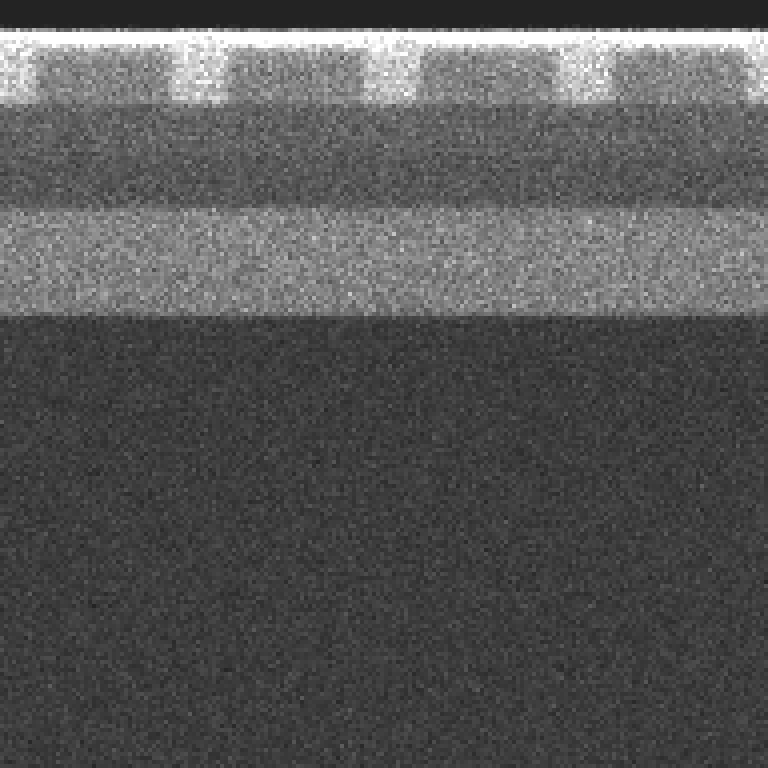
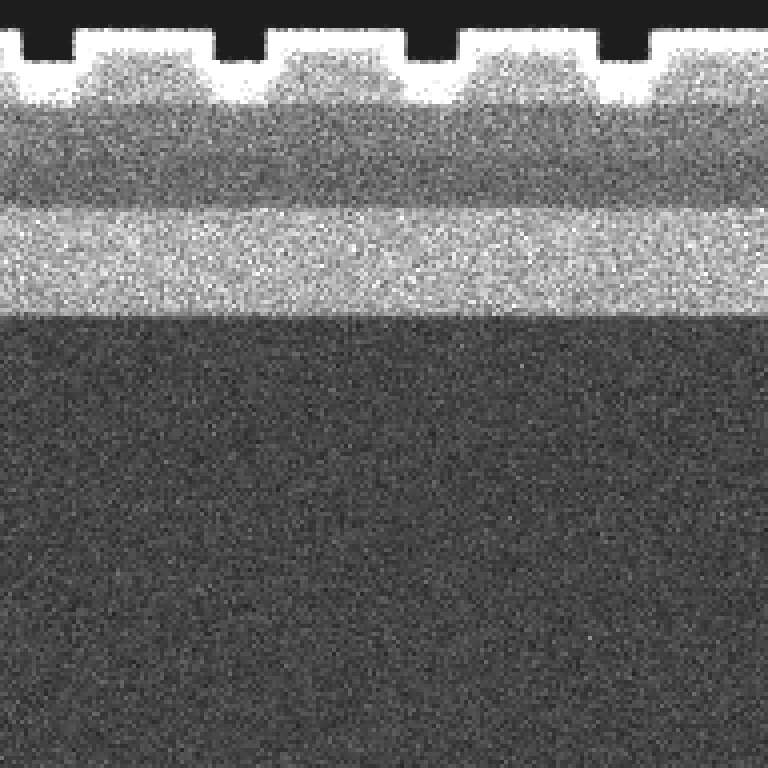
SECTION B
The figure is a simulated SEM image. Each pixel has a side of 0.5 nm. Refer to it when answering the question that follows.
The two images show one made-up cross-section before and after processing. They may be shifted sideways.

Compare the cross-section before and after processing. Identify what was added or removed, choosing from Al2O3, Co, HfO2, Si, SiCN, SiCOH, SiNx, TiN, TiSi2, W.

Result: W removed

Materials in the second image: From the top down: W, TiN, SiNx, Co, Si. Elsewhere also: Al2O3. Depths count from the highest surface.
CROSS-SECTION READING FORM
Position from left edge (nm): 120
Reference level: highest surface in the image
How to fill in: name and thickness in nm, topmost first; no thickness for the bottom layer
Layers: empty 16, W 20, TiN 26, SiNx 26, Co 54, Si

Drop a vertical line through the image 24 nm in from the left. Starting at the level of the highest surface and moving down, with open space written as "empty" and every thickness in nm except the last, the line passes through empty 16, W 20, TiN 26, SiNx 26, Co 54, Si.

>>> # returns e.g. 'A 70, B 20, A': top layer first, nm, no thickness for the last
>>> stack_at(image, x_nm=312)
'empty 16, W 20, TiN 26, SiNx 26, Co 54, Si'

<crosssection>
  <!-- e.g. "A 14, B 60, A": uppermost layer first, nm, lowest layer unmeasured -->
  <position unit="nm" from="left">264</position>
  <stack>Al2O3 36, TiN 26, SiNx 26, Co 54, Si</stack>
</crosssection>